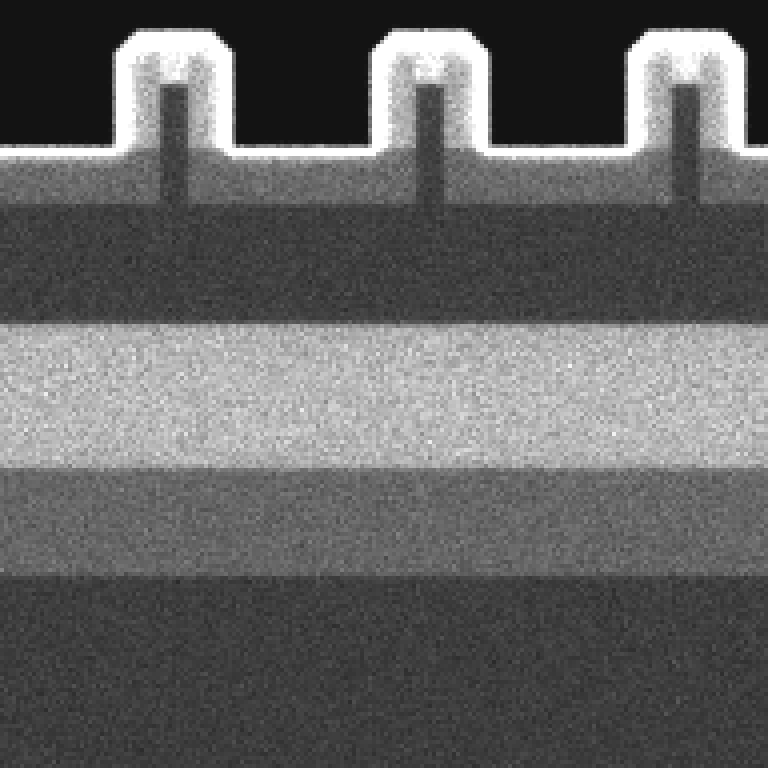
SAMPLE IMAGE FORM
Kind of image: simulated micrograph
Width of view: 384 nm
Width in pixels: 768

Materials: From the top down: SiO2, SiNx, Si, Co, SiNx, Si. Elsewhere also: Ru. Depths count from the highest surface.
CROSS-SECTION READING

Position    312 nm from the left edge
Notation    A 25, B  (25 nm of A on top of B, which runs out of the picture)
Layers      empty 58, SiNx 28, Si 60, Co 72, SiNx 54, Si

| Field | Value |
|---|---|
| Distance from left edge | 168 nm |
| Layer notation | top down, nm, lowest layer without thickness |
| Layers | empty 58, SiNx 28, Si 60, Co 72, SiNx 54, Si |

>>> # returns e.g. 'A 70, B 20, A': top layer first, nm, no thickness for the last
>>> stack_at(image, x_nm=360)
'SiO2 58, SiNx 28, Si 60, Co 72, SiNx 54, Si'